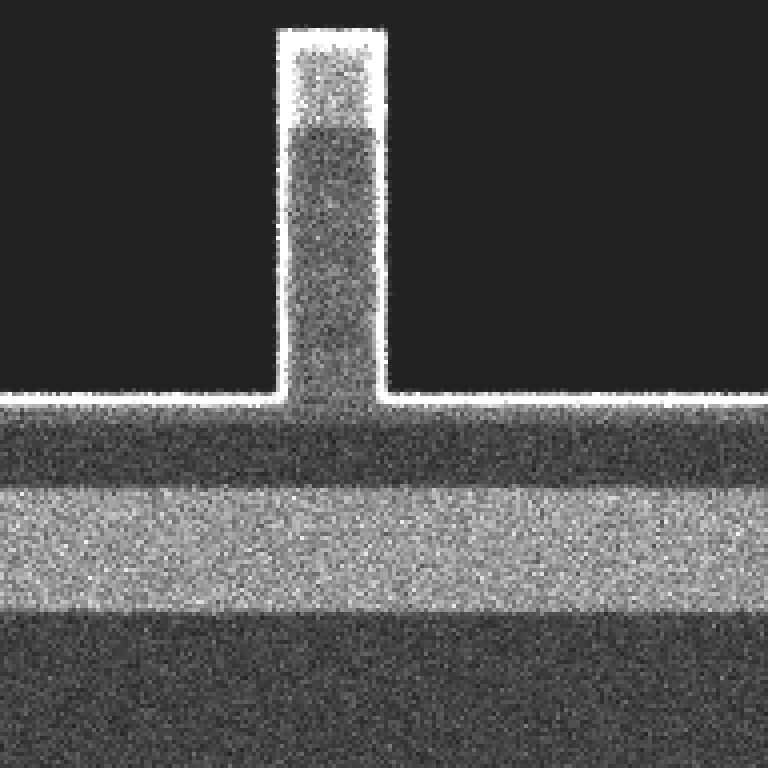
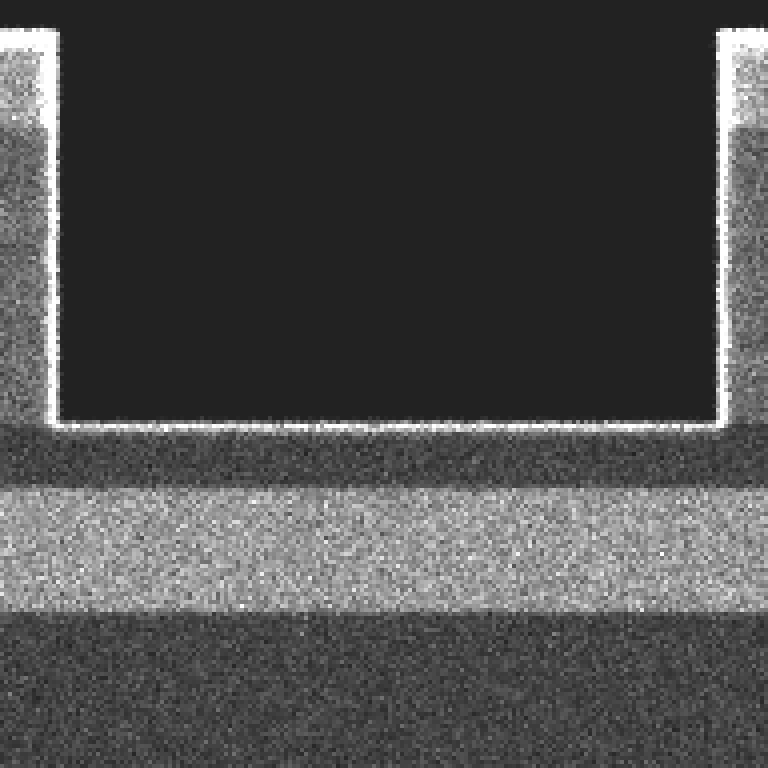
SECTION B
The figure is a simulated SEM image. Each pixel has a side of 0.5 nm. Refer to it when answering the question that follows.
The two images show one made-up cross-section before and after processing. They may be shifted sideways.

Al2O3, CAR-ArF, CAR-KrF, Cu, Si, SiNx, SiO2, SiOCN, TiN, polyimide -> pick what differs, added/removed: SiNx removed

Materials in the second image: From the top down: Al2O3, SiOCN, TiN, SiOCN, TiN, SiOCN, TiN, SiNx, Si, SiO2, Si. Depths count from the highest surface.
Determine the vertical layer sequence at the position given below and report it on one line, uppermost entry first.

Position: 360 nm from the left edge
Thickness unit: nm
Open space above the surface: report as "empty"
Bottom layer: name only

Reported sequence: Al2O3 48, SiOCN 30, TiN 24, SiOCN 16, TiN 24, SiOCN 16, TiN 24, SiNx 14, Si 32, SiO2 62, Si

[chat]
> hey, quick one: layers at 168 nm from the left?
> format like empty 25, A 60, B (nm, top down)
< empty 196, Si 32, SiO2 62, Si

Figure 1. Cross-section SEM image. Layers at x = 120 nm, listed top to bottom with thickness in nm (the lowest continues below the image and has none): empty 196, Si 32, SiO2 62, Si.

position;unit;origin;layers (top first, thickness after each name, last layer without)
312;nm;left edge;empty 196, Si 32, SiO2 62, Si